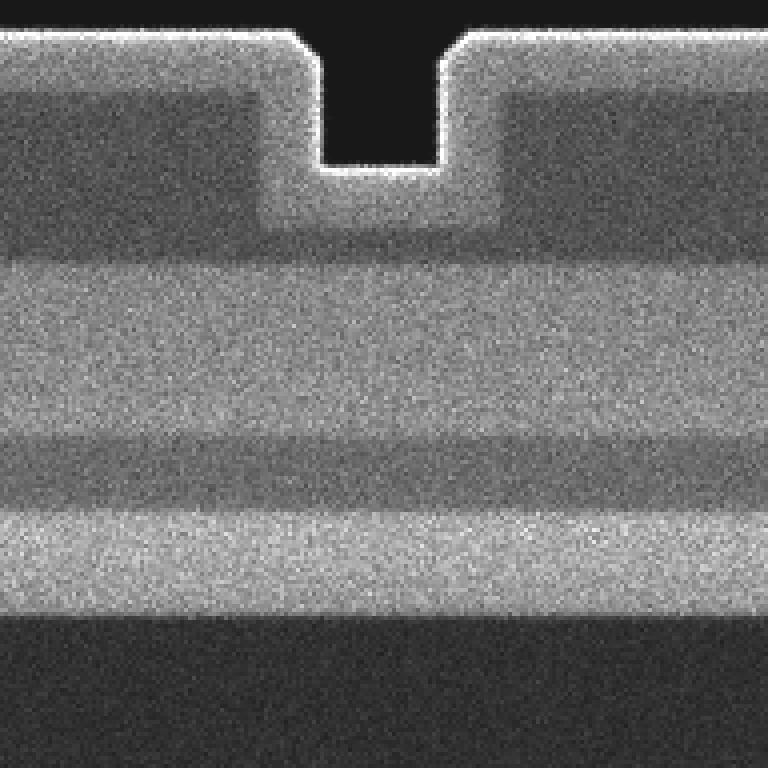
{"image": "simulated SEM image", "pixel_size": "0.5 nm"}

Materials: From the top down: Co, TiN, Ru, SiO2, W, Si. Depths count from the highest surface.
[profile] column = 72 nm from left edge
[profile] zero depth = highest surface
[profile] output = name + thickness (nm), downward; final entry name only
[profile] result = Co 30, TiN 86, Ru 86, SiO2 38, W 52, Si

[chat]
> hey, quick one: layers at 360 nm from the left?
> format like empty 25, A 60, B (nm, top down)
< Co 30, TiN 86, Ru 86, SiO2 38, W 52, Si